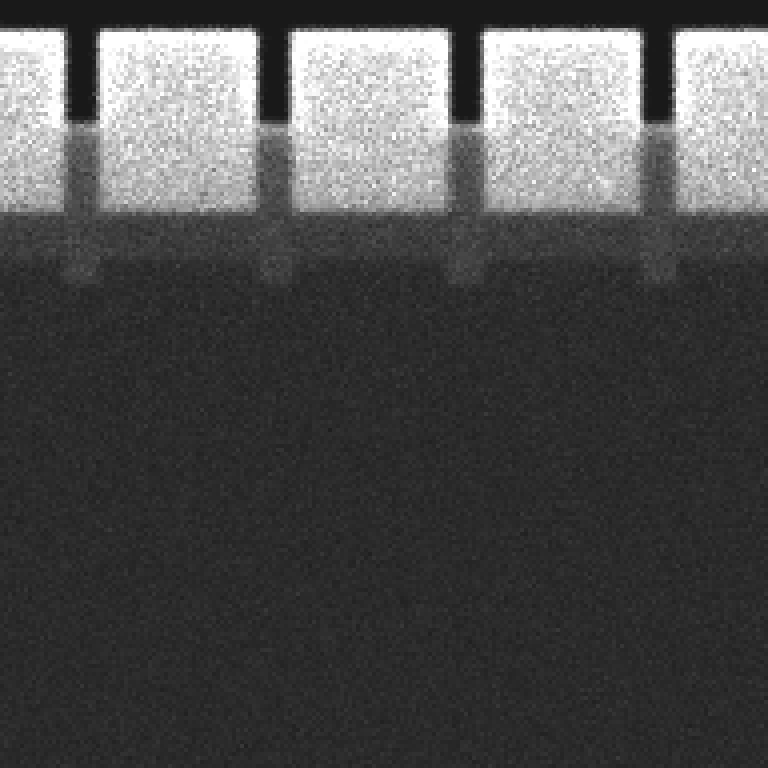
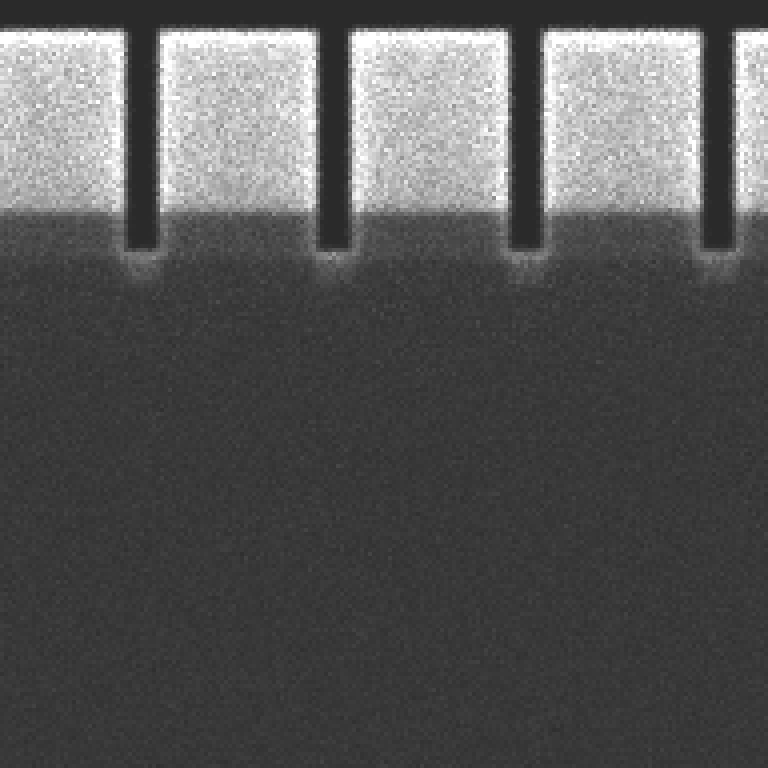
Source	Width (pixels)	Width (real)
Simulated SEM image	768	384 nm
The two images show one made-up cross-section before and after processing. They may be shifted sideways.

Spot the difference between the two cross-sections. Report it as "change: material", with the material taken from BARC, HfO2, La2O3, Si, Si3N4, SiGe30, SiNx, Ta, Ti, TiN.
removed: Si3N4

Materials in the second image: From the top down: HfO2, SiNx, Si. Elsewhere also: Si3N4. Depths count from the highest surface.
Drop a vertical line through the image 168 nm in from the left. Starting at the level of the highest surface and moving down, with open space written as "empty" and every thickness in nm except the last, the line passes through empty 110, Si3N4 16, Si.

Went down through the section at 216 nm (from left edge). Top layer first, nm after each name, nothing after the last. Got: HfO2 90, SiNx 24, Si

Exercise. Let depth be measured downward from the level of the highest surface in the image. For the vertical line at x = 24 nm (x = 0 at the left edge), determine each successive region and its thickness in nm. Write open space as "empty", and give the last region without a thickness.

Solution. HfO2 90, SiNx 24, Si